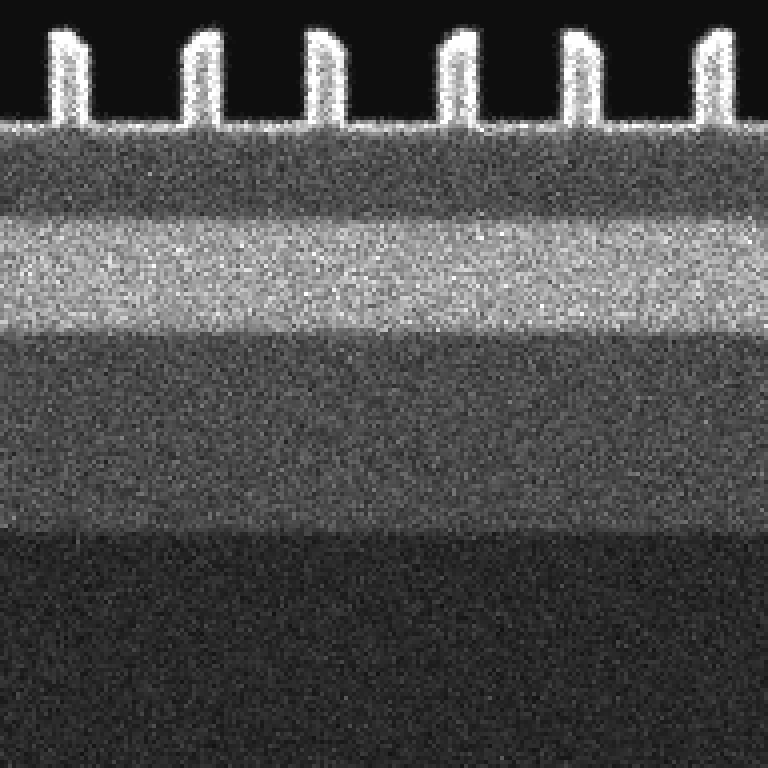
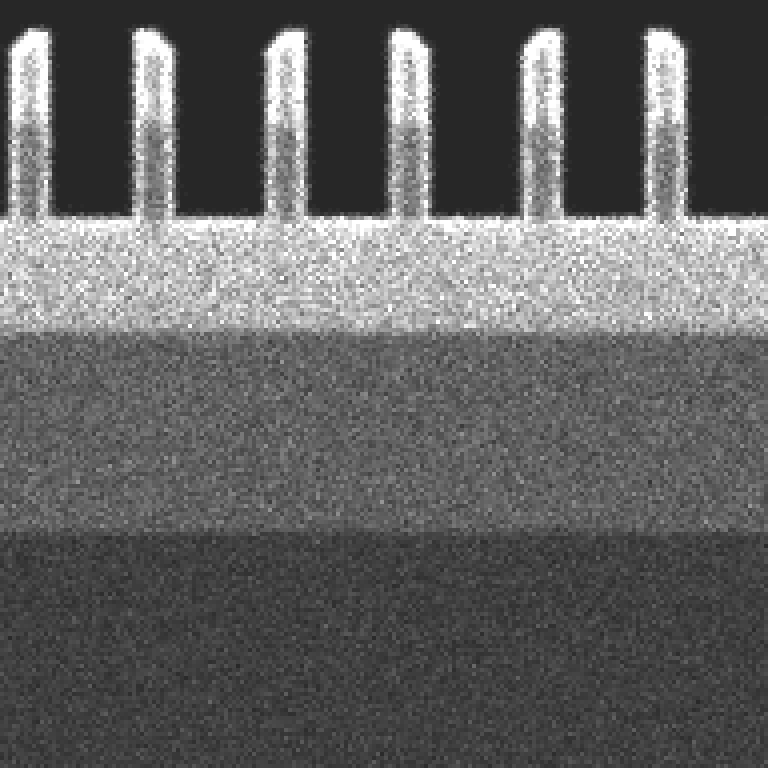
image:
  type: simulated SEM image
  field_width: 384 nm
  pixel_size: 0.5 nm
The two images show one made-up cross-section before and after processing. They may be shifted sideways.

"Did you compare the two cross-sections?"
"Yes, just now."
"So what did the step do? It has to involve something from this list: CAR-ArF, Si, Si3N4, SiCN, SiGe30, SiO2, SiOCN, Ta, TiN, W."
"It removed TiN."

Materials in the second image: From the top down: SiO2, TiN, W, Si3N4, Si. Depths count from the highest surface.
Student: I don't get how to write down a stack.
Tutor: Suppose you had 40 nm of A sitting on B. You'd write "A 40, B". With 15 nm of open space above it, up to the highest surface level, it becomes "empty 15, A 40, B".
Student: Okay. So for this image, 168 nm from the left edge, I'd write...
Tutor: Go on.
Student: empty 94, W 56, Si3N4 100, Si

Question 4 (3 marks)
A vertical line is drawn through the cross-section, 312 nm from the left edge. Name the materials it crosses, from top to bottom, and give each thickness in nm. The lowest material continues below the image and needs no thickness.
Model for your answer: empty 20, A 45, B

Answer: empty 94, W 56, Si3N4 100, Si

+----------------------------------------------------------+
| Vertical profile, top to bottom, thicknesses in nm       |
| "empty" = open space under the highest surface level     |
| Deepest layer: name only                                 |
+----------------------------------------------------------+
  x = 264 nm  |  empty 6, SiO2 40, TiN 48, W 56, Si3N4 100, Si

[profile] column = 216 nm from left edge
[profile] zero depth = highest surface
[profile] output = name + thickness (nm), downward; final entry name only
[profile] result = empty 94, W 56, Si3N4 100, Si